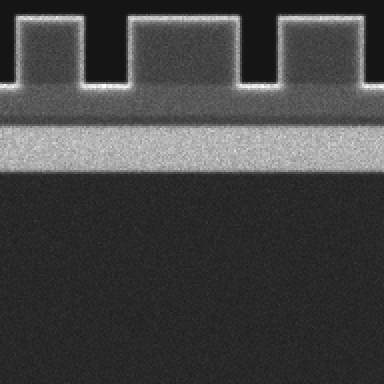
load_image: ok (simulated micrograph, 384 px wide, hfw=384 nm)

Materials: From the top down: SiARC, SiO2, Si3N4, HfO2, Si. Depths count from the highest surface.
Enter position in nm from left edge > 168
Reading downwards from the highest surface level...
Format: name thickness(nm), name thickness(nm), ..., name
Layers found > SiARC 68, SiO2 32, Si3N4 10, HfO2 46, Si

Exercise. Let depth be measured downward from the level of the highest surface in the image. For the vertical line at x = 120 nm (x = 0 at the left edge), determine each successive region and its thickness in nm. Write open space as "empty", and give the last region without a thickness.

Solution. empty 68, SiO2 32, Si3N4 10, HfO2 46, Si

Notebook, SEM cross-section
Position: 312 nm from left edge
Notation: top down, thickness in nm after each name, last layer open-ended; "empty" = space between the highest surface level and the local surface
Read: SiARC 68, SiO2 32, Si3N4 10, HfO2 46, Si